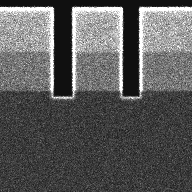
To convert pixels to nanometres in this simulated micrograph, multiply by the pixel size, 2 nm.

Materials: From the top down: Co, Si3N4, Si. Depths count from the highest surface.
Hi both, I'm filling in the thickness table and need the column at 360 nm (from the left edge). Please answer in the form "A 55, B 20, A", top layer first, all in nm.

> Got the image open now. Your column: Co 88, Si3N4 78, Si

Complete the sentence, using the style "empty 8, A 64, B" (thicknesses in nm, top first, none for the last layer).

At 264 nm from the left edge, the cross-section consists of empty 178, Si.